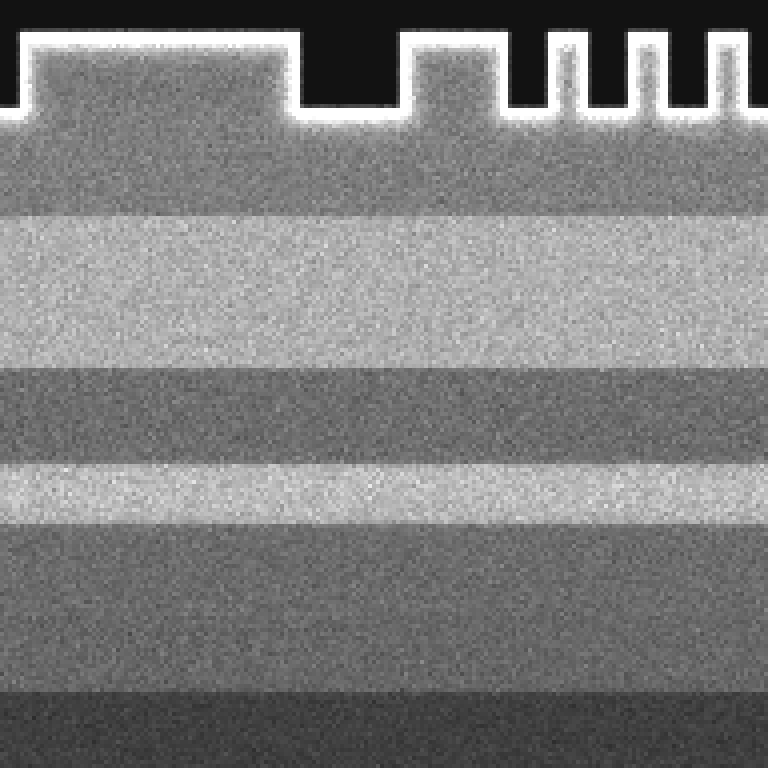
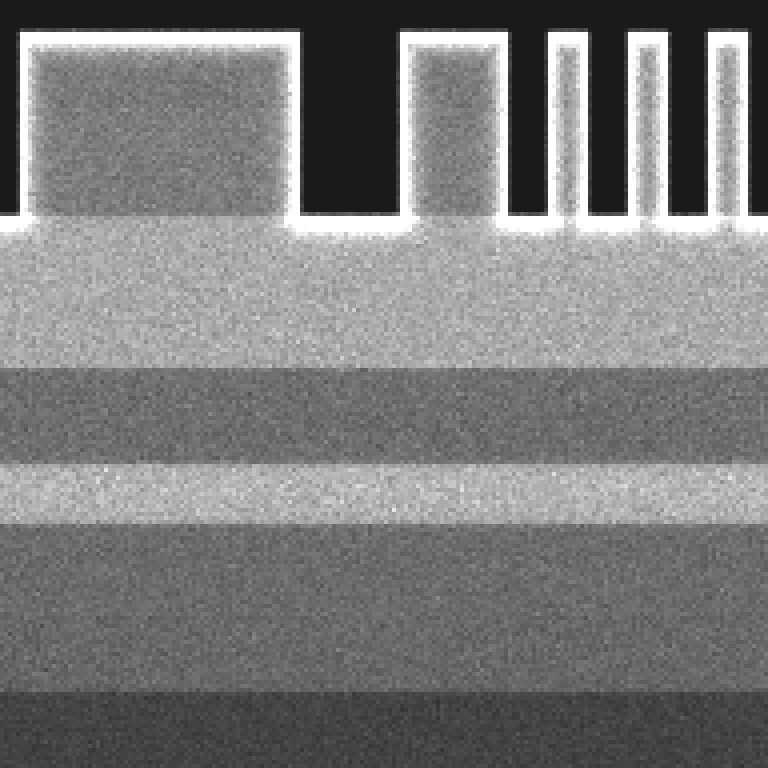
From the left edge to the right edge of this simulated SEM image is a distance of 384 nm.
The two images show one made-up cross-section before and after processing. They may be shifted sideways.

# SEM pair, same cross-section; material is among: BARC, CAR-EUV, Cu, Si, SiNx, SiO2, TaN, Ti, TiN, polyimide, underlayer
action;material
removed;underlayer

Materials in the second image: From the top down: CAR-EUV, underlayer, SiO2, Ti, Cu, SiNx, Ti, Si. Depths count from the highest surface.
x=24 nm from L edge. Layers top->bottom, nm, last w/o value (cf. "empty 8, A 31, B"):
CAR-EUV 38, underlayer 54, SiO2 76, Ti 48, Cu 30, SiNx 46, Ti 38, Si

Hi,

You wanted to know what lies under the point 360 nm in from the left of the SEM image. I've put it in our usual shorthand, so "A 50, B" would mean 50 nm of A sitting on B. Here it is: CAR-EUV 38, underlayer 54, SiO2 76, Ti 48, Cu 30, SiNx 46, Ti 38, Si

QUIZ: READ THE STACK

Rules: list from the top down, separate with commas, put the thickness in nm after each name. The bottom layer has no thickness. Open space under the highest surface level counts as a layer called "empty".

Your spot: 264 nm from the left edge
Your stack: empty 92, SiO2 76, Ti 48, Cu 30, SiNx 46, Ti 38, Si